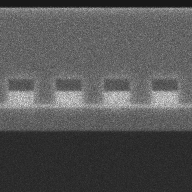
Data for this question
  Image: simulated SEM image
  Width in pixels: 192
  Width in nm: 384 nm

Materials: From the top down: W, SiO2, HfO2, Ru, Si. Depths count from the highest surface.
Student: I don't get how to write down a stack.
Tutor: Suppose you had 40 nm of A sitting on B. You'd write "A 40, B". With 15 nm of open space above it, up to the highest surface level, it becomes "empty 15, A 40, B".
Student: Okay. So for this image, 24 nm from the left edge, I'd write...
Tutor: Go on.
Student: W 142, SiO2 24, HfO2 34, Ru 46, Si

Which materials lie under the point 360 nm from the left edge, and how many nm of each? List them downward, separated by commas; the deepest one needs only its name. W 192, HfO2 8, Ru 46, Si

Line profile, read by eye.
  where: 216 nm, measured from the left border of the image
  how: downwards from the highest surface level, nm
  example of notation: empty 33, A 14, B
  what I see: W 142, SiO2 24, HfO2 34, Ru 46, Si